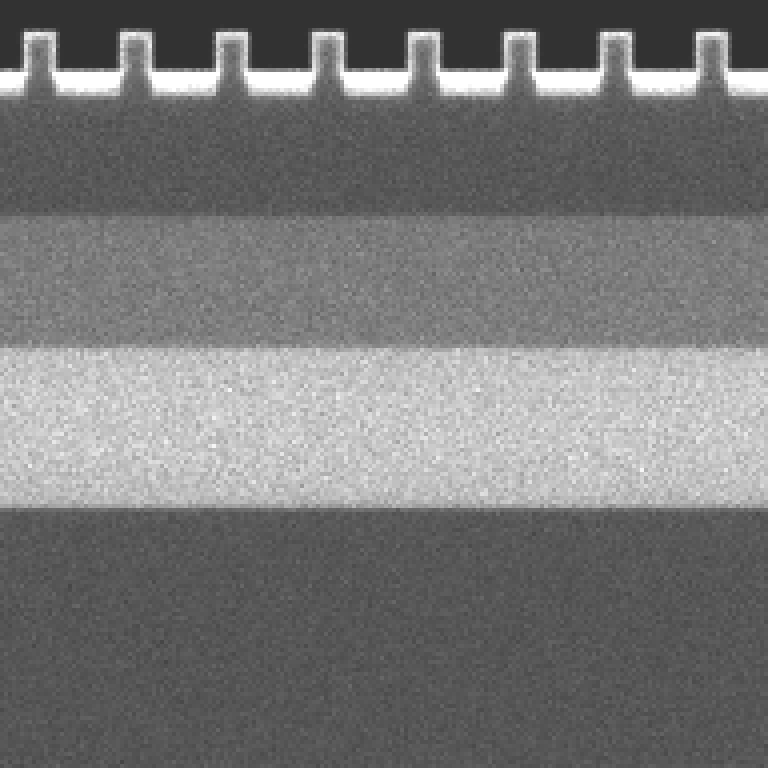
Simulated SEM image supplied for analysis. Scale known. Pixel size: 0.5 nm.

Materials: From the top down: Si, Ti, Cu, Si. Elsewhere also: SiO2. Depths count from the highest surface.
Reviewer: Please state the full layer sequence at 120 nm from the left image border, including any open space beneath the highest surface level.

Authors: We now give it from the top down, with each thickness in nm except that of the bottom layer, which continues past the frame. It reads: Si 92, Ti 66, Cu 80, Si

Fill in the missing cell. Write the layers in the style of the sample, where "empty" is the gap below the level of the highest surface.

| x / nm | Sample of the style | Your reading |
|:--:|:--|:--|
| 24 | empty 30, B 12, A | Si 92, Ti 66, Cu 80, Si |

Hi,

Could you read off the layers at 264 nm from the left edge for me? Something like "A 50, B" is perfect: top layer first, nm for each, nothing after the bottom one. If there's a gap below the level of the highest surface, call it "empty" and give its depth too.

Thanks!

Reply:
Si 92, Ti 66, Cu 80, Si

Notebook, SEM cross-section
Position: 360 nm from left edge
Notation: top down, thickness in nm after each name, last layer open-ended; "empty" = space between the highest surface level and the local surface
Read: Si 92, Ti 66, Cu 80, Si